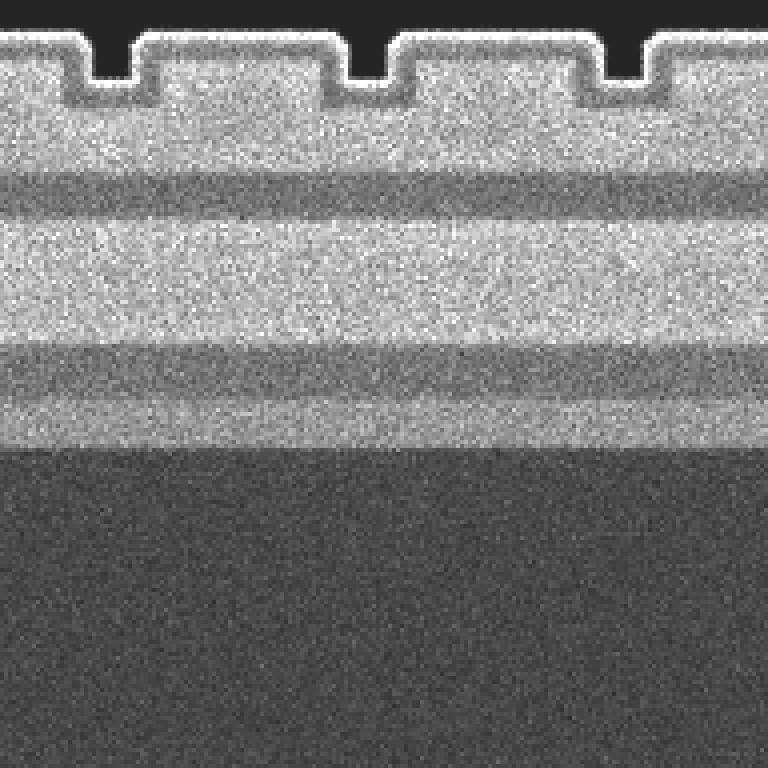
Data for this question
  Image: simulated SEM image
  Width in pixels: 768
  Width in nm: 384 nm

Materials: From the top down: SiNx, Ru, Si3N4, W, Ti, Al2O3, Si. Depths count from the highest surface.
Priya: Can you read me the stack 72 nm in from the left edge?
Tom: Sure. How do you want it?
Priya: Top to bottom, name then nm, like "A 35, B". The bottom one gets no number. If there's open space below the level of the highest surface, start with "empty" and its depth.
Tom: SiNx 38, Ru 32, Si3N4 24, W 62, Ti 28, Al2O3 24, Si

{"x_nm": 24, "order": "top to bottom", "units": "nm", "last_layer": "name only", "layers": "SiNx 14, Ru 56, Si3N4 24, W 62, Ti 28, Al2O3 24, Si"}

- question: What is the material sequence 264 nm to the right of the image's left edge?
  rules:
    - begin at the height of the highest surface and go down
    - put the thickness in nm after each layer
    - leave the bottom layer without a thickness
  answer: SiNx 14, Ru 56, Si3N4 24, W 62, Ti 28, Al2O3 24, Si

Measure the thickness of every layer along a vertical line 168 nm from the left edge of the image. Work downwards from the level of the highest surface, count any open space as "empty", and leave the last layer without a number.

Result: empty 2, SiNx 36, Ru 32, Si3N4 24, W 62, Ti 28, Al2O3 24, Si